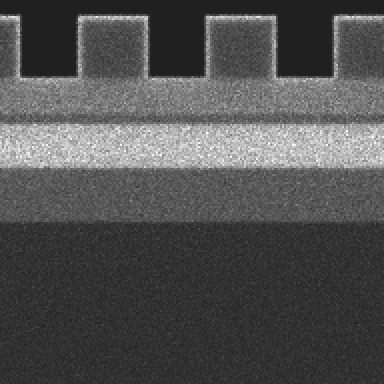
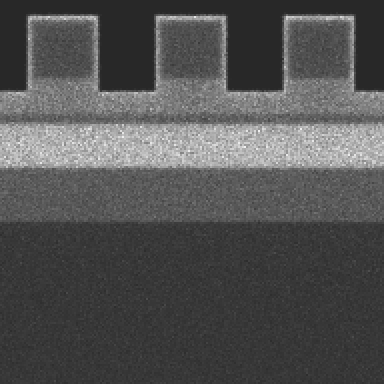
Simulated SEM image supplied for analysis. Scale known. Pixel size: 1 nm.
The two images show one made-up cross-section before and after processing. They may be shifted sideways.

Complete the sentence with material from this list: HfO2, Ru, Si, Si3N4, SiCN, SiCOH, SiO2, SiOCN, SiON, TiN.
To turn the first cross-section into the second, Ru must be removed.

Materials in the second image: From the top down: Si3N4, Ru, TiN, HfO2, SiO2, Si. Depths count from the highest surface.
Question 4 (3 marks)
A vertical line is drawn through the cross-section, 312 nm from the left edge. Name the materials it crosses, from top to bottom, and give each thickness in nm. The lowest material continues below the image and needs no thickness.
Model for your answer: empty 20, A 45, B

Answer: Si3N4 62, Ru 36, TiN 10, HfO2 44, SiO2 54, Si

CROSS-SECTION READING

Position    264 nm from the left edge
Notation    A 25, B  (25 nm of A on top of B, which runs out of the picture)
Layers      empty 76, Ru 22, TiN 10, HfO2 44, SiO2 54, Si